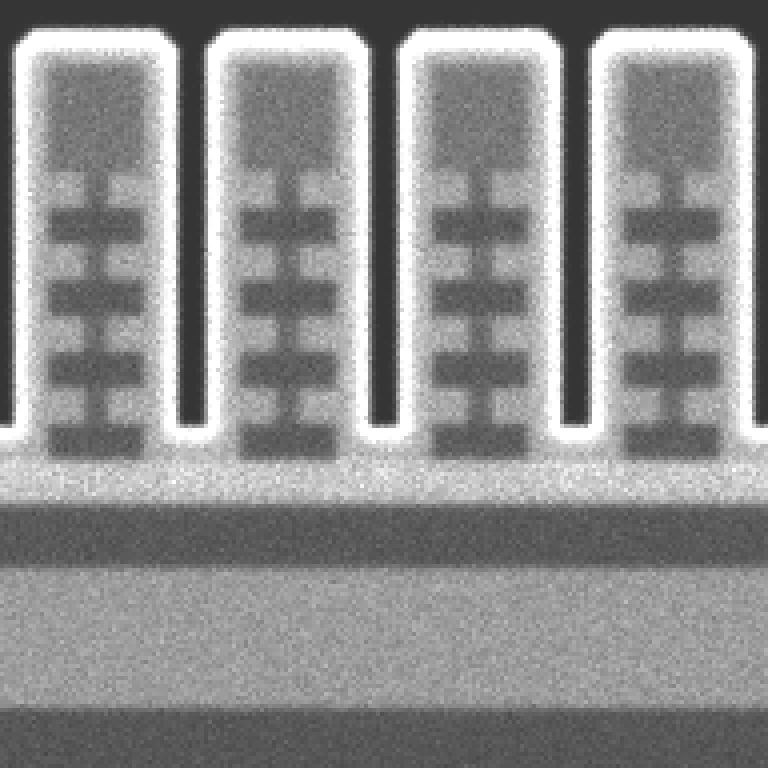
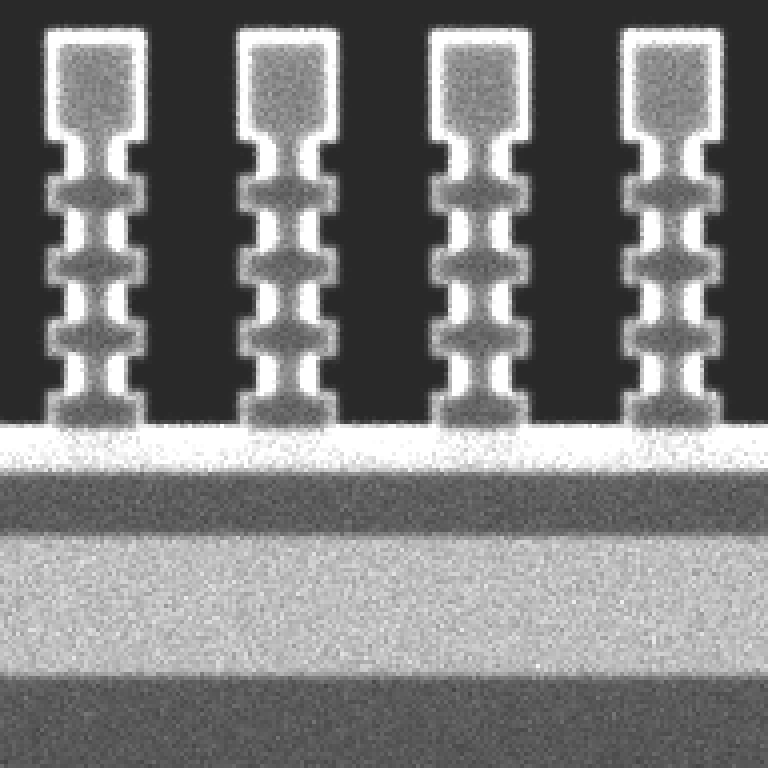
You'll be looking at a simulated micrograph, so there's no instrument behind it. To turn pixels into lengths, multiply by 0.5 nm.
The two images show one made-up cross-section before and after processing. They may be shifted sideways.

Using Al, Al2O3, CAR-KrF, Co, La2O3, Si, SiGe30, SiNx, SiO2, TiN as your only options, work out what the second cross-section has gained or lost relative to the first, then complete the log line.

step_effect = removed Al2O3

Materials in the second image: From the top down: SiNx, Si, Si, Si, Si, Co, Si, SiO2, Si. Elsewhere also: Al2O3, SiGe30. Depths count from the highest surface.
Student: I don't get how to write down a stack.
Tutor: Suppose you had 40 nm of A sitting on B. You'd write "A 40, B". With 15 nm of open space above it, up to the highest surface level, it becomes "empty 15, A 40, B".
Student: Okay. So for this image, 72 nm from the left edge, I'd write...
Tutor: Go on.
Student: empty 198, Co 22, Si 32, SiO2 70, Si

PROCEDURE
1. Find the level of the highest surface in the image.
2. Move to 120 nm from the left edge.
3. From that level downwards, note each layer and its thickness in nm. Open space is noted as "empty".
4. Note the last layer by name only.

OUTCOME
SiNx 54, empty 18, Si 18, empty 18, Si 18, empty 18, Si 18, empty 18, Si 18, Co 22, Si 32, SiO2 70, Si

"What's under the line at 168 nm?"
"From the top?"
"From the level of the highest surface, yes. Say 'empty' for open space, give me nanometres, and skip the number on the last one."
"empty 198, Co 22, Si 32, SiO2 70, Si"